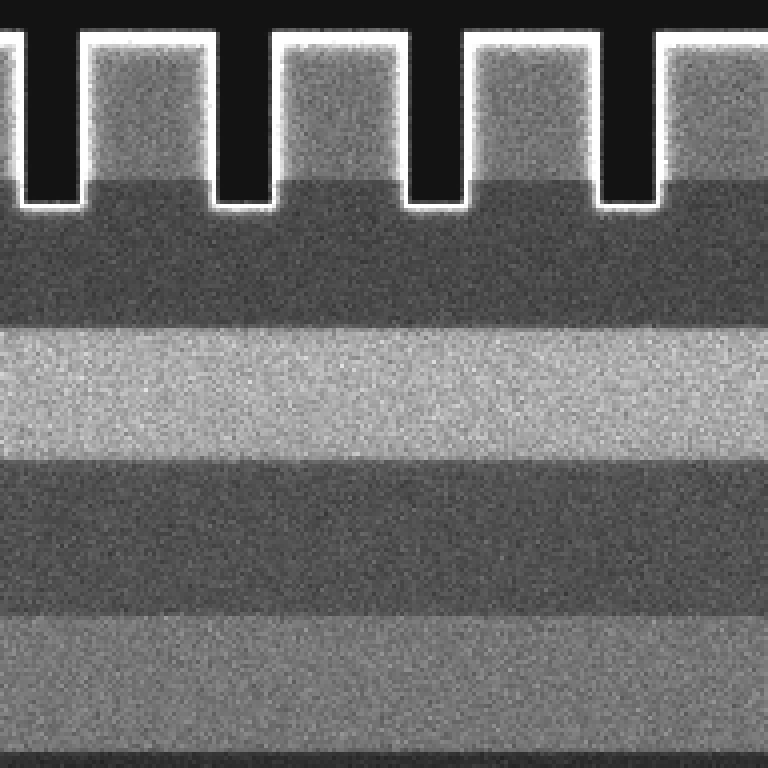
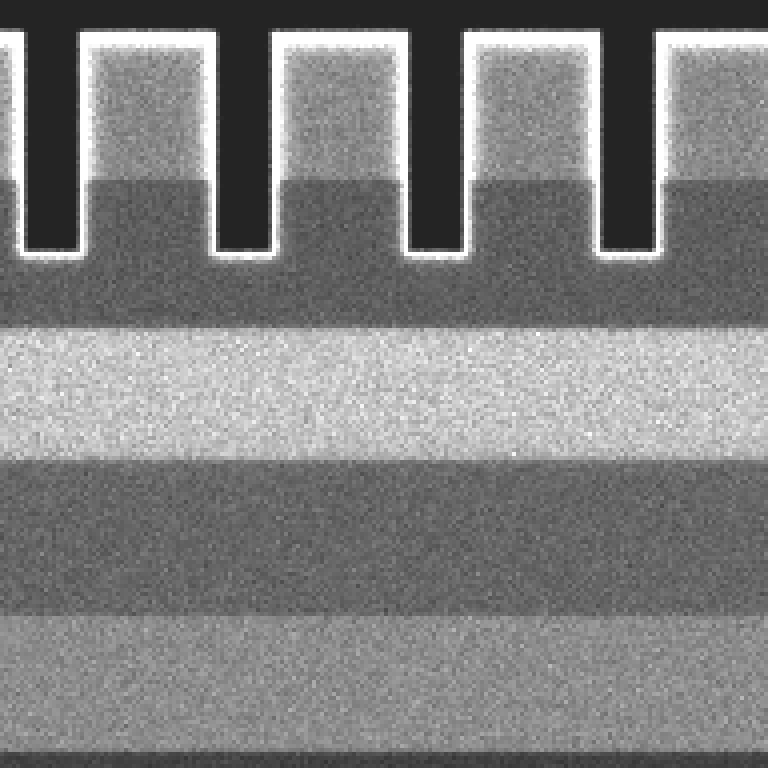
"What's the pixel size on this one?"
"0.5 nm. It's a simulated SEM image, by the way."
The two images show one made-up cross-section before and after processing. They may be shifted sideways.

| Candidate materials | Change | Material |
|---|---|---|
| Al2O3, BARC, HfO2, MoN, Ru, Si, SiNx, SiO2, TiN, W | removed | SiNx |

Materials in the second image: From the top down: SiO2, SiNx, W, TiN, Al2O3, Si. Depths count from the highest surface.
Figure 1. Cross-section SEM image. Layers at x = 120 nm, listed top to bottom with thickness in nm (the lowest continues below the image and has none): empty 110, SiNx 38, W 66, TiN 78, Al2O3 68, Si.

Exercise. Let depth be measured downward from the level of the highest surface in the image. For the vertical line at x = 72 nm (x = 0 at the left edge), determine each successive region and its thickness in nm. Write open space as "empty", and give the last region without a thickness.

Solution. SiO2 74, SiNx 74, W 66, TiN 78, Al2O3 68, Si